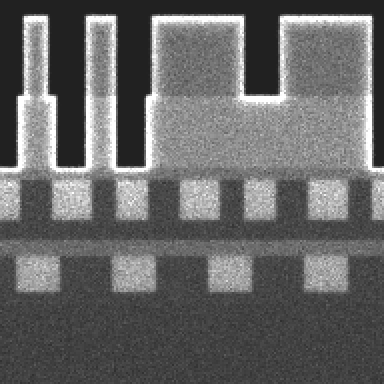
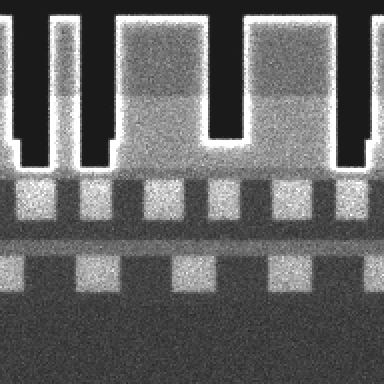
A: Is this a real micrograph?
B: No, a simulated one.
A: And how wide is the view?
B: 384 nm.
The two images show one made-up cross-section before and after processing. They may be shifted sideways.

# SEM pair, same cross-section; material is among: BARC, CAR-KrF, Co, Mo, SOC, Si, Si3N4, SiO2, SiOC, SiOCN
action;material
removed;SiO2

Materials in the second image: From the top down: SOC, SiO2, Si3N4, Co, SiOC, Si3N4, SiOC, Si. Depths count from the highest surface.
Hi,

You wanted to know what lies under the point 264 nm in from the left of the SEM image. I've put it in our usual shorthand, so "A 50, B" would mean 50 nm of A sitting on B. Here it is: SOC 80, SiO2 72, Si3N4 12, SiOC 60, Si3N4 16, SiOC 48, Si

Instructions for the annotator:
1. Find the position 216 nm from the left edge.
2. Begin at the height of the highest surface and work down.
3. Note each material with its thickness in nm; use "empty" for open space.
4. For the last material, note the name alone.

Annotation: empty 124, SiO2 28, Si3N4 12, Co 40, SiOC 20, Si3N4 16, SiOC 48, Si